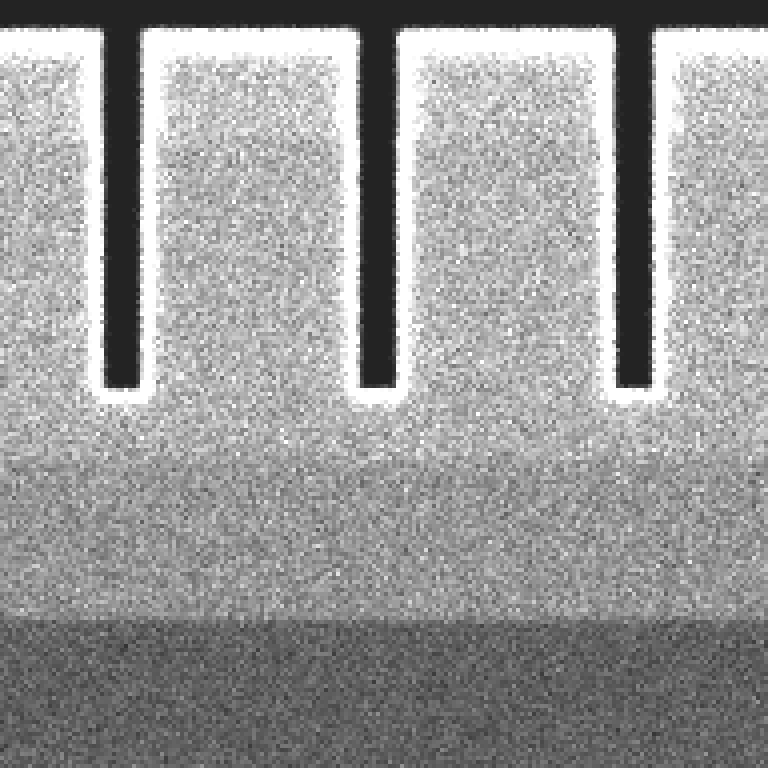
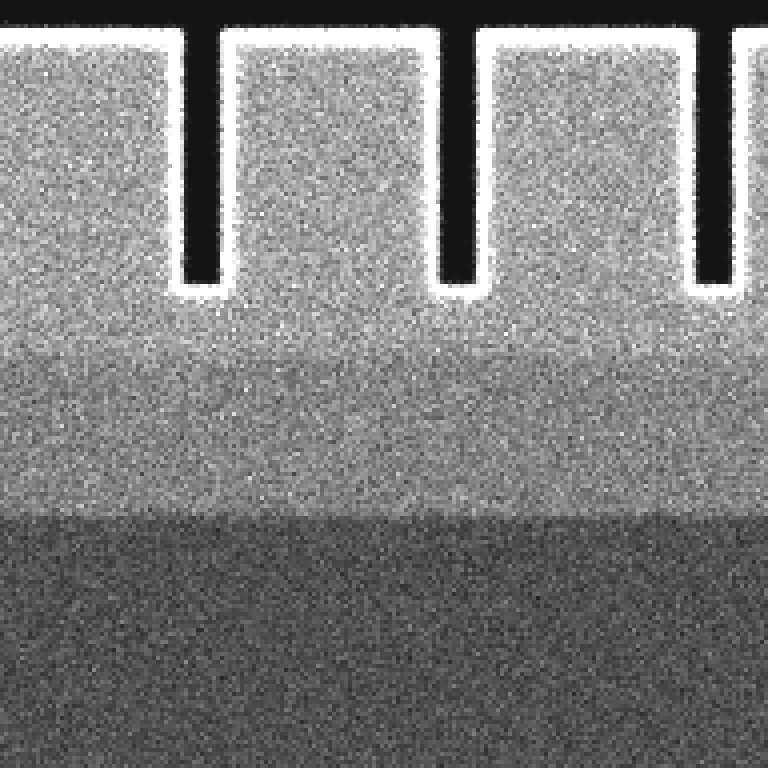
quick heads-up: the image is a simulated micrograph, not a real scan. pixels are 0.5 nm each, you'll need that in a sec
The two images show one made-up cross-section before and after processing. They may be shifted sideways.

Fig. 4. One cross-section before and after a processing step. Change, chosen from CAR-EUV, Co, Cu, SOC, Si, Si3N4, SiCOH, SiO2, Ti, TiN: SOC removed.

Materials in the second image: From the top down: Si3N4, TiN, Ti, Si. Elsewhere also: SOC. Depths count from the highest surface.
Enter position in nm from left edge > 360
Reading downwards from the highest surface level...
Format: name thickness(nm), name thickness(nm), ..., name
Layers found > empty 128, TiN 34, Ti 80, Si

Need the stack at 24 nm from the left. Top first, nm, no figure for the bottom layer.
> Si3N4 88, TiN 74, Ti 80, Si